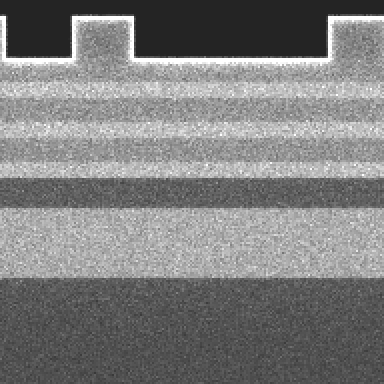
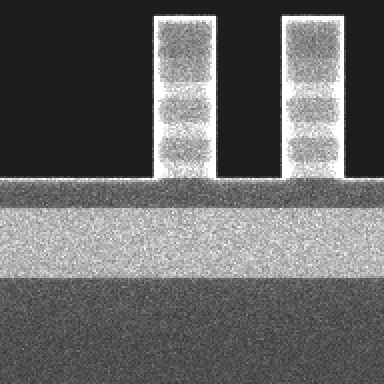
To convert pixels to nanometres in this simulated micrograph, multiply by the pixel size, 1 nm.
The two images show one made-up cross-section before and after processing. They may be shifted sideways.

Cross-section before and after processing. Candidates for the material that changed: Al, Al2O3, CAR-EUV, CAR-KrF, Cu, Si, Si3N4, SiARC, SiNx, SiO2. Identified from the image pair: Al2O3 and Si3N4 (removed).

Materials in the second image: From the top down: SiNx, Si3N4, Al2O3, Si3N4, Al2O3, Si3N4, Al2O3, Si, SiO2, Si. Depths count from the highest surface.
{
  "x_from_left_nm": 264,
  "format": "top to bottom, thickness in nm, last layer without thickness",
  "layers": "empty 162, Si 30, SiO2 70, Si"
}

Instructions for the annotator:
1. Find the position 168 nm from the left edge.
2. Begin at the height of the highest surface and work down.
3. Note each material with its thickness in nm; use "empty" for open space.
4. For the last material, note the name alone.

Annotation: SiNx 42, Si3N4 24, Al2O3 16, Si3N4 24, Al2O3 16, Si3N4 24, Al2O3 16, Si 30, SiO2 70, Si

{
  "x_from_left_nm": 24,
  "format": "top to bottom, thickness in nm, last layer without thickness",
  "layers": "empty 162, Si 30, SiO2 70, Si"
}